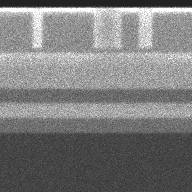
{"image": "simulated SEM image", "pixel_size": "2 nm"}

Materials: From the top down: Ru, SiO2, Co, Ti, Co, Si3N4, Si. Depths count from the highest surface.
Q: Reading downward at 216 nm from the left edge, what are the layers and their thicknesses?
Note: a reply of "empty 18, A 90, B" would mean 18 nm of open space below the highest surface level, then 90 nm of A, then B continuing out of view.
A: Ru 80, SiO2 10, Co 72, Ti 28, Co 30, Si3N4 30, Si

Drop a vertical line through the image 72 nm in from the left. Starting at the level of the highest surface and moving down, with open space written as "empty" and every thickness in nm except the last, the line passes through Ru 80, SiO2 10, Co 72, Ti 28, Co 30, Si3N4 30, Si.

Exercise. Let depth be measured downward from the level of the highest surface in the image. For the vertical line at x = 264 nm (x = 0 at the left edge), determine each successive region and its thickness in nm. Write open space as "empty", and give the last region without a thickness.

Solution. SiO2 90, Co 72, Ti 28, Co 30, Si3N4 30, Si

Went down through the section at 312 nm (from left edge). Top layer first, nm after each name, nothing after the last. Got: SiO2 90, Co 72, Ti 28, Co 30, Si3N4 30, Si